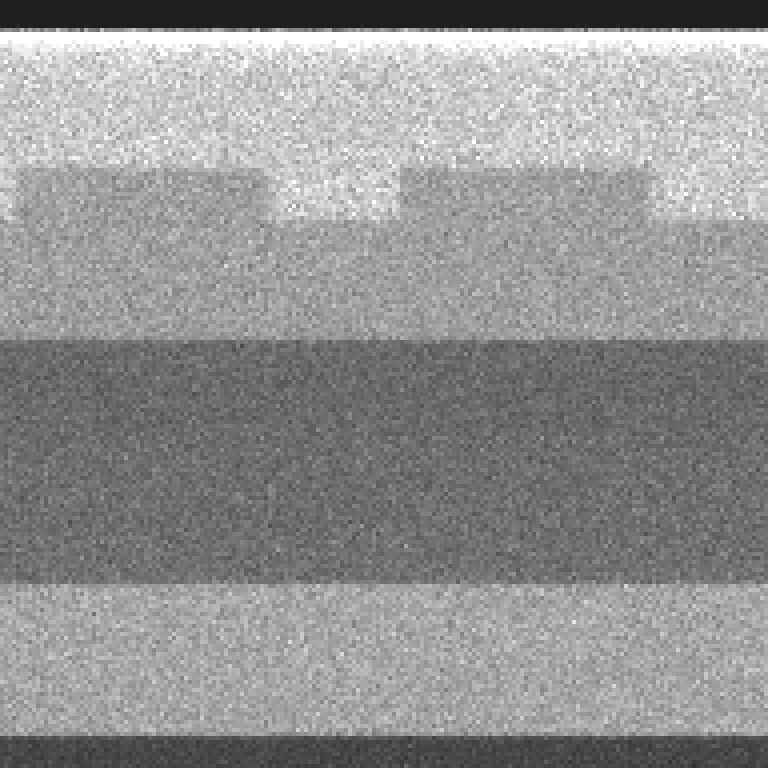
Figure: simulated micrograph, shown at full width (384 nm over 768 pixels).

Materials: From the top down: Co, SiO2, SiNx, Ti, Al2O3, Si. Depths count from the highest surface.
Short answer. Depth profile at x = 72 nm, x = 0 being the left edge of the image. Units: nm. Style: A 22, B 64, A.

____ Co 68, SiO2 86, SiNx 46, Ti 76, Al2O3 76, Si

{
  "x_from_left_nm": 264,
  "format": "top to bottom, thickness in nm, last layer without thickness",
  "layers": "Co 68, SiO2 86, SiNx 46, Ti 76, Al2O3 76, Si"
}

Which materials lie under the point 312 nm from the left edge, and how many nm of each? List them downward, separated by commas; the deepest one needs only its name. Co 68, SiO2 86, SiNx 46, Ti 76, Al2O3 76, Si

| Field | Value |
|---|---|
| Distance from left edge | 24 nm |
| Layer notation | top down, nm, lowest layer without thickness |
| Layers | Co 68, SiO2 86, SiNx 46, Ti 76, Al2O3 76, Si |